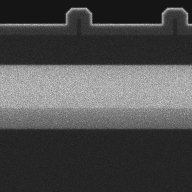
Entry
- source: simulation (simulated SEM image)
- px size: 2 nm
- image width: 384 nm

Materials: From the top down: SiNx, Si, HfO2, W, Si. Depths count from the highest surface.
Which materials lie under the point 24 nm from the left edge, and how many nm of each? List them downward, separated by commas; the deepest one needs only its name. empty 32, SiNx 22, Si 60, HfO2 86, W 42, Si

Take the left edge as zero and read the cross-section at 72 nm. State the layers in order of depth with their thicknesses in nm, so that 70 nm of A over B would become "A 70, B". empty 32, SiNx 22, Si 60, HfO2 86, W 42, Si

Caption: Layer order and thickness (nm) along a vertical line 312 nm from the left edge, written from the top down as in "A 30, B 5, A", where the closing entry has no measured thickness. empty 32, SiNx 22, Si 60, HfO2 86, W 42, Si